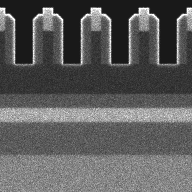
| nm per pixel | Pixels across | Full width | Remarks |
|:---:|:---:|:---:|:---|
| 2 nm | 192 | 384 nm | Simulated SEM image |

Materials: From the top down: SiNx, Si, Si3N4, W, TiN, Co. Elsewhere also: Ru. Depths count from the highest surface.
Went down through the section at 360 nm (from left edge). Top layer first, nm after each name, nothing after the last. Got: empty 16, SiNx 96, Si 60, Si3N4 28, W 28, TiN 66, Co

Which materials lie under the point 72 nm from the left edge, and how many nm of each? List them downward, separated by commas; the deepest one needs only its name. empty 16, SiNx 96, Si 60, Si3N4 28, W 28, TiN 66, Co